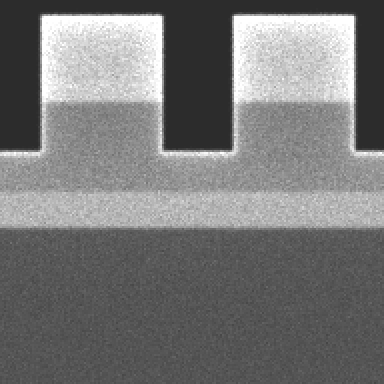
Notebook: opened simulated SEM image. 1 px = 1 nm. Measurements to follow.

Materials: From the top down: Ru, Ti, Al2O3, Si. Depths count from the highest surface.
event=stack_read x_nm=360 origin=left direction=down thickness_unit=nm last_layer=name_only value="empty 136, Ti 40, Al2O3 36, Si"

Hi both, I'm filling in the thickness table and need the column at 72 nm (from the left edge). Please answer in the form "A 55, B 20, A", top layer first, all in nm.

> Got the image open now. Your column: Ru 86, Ti 90, Al2O3 36, Si